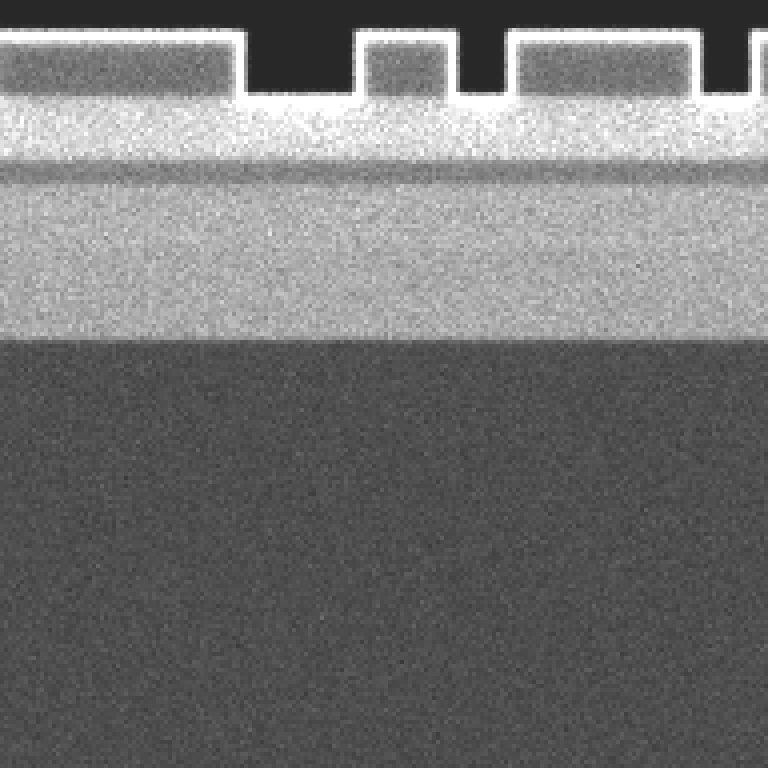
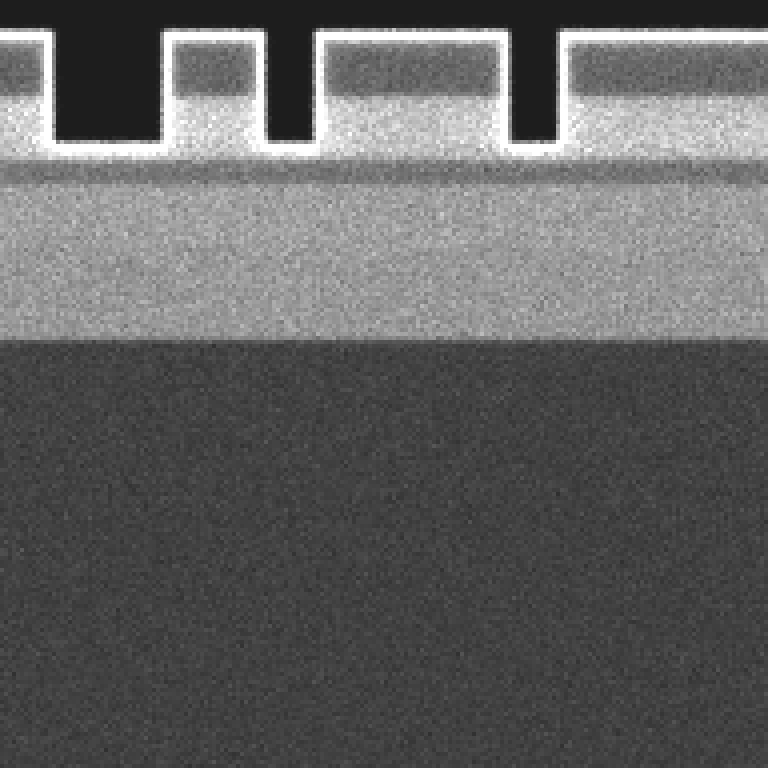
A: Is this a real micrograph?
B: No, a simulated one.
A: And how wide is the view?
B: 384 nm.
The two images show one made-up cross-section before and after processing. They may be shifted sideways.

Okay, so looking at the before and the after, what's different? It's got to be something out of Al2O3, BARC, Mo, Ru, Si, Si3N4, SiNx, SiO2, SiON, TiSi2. Ru, removed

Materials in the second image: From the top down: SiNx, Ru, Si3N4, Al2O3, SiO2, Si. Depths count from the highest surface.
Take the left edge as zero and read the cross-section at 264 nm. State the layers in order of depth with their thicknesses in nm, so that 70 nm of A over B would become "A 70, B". empty 56, Ru 8, Si3N4 12, Al2O3 32, SiO2 46, Si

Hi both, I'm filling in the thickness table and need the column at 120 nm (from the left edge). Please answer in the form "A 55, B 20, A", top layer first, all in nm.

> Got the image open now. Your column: SiNx 32, Ru 32, Si3N4 12, Al2O3 32, SiO2 46, Si